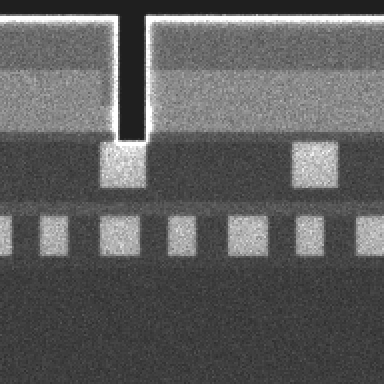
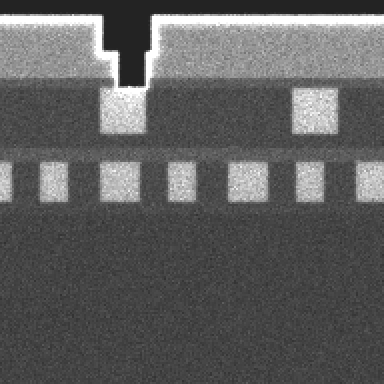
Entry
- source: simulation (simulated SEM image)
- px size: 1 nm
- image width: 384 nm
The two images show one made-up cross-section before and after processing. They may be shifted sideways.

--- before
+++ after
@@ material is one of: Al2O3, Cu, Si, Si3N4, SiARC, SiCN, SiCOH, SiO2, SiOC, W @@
SiARC removed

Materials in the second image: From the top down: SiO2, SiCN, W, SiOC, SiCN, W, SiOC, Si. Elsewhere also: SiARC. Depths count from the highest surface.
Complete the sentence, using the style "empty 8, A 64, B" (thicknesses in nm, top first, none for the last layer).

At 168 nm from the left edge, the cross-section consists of SiO2 62, SiCN 10, SiOC 60, SiCN 14, W 40, SiOC 12, Si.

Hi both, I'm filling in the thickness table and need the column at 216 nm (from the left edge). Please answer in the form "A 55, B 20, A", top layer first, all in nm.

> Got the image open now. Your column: SiO2 62, SiCN 10, SiOC 60, SiCN 14, SiOC 52, Si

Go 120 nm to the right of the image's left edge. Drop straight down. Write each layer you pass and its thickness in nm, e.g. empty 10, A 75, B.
empty 72, W 46, SiOC 14, SiCN 14, W 40, SiOC 12, Si